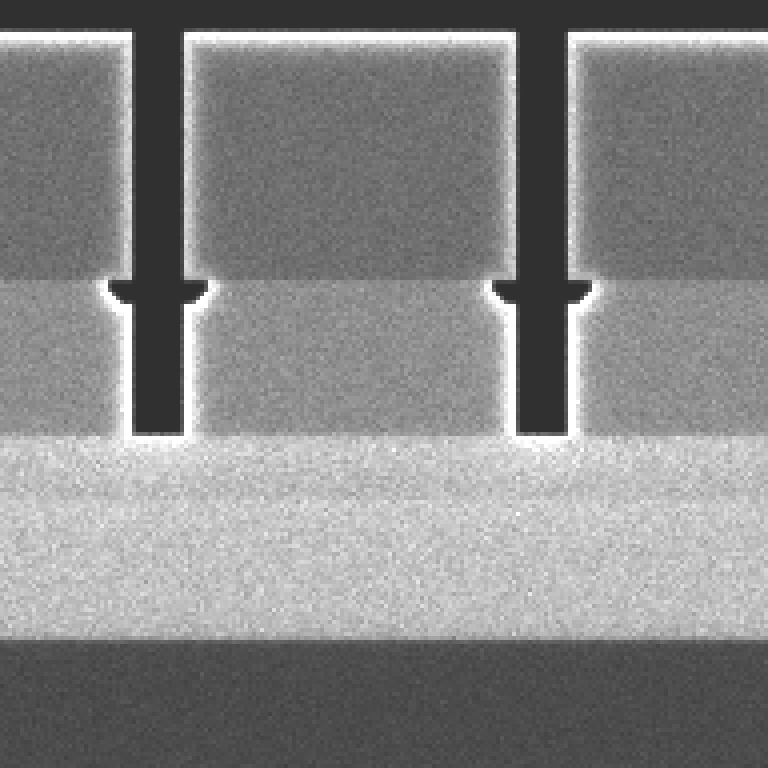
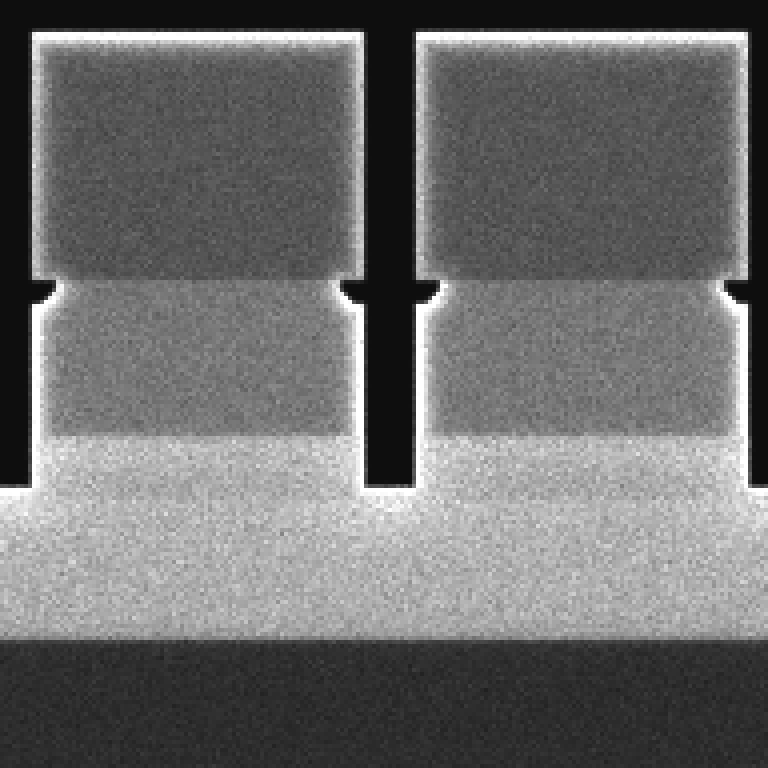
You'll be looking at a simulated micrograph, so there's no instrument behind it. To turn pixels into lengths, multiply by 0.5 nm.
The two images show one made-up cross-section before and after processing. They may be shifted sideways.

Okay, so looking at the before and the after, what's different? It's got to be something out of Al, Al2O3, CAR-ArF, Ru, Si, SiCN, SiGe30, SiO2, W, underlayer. Ru, removed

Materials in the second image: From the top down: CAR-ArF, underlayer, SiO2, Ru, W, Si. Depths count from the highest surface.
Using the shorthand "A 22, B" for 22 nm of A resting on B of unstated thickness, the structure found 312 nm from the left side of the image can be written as CAR-ArF 64, underlayer 60, SiO2 78, Ru 32, W 70, Si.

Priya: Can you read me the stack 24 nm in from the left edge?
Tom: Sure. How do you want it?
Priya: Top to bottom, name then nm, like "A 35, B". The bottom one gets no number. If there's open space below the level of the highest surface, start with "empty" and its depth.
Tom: CAR-ArF 64, underlayer 60, empty 8, SiO2 70, Ru 32, W 70, Si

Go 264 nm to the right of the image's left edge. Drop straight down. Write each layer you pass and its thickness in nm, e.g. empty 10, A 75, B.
CAR-ArF 64, underlayer 60, SiO2 78, Ru 32, W 70, Si